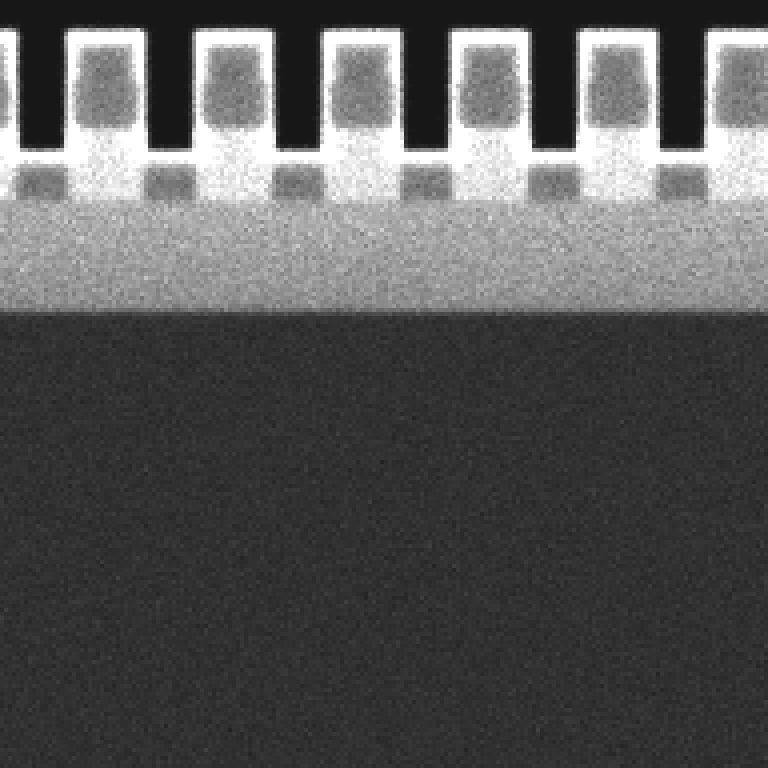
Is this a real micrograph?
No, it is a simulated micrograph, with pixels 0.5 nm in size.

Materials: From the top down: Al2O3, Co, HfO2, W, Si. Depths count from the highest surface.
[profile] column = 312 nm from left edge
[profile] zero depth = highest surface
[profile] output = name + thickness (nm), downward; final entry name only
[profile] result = Al2O3 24, Co 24, HfO2 36, W 56, Si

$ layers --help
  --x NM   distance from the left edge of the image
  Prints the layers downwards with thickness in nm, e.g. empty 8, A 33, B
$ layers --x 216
empty 60, Al2O3 24, W 56, Si